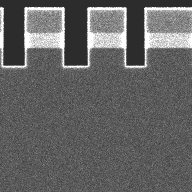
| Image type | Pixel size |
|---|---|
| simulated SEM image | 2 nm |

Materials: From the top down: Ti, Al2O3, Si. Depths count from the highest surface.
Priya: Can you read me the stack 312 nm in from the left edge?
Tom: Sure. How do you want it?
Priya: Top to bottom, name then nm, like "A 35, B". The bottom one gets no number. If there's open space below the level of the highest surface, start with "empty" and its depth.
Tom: Ti 50, Al2O3 30, Si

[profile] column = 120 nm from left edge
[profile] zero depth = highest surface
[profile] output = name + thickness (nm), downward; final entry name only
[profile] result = Ti 50, Al2O3 30, Si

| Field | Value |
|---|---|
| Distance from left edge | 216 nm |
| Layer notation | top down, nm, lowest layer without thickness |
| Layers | Ti 50, Al2O3 30, Si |